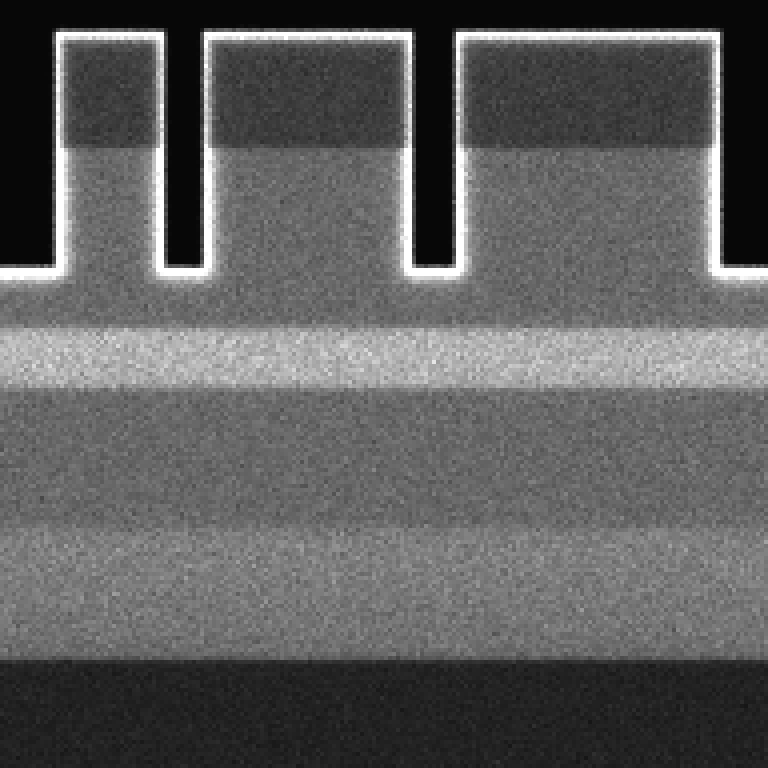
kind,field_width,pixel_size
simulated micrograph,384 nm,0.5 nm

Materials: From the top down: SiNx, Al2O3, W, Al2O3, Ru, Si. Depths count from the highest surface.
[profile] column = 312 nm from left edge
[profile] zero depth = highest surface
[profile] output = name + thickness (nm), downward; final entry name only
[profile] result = SiNx 58, Al2O3 90, W 30, Al2O3 70, Ru 66, Si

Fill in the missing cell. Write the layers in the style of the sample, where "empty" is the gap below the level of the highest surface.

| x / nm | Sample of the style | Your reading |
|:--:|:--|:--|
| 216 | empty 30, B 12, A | empty 118, Al2O3 30, W 30, Al2O3 70, Ru 66, Si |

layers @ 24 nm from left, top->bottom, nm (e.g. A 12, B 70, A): empty 118, Al2O3 30, W 30, Al2O3 70, Ru 66, Si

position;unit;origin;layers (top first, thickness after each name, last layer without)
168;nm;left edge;SiNx 58, Al2O3 90, W 30, Al2O3 70, Ru 66, Si